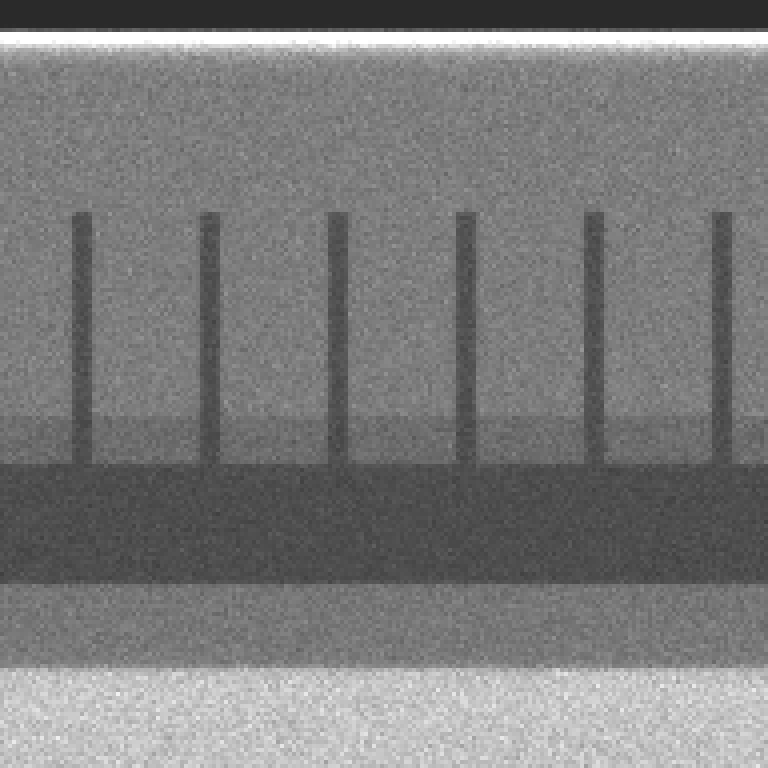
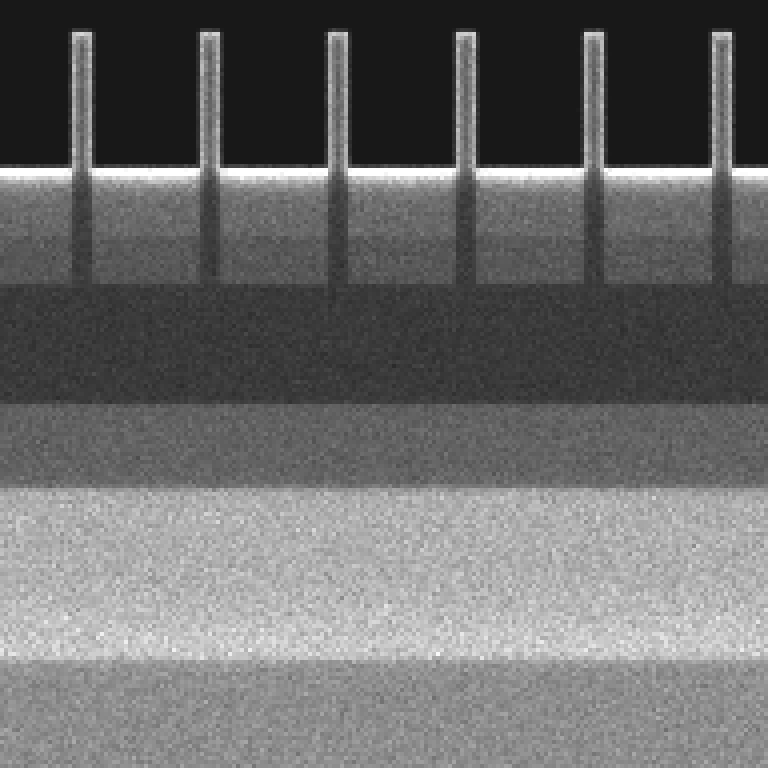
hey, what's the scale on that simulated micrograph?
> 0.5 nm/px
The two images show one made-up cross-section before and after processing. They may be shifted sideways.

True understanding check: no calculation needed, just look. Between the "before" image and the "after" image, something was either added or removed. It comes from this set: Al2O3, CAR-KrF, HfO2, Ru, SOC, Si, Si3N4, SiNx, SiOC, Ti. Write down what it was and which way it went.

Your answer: SOC (removed)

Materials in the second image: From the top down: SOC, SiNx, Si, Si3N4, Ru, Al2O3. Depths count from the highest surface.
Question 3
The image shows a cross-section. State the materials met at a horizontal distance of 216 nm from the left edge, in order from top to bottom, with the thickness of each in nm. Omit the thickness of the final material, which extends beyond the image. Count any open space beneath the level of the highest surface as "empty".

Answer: empty 68, SOC 34, SiNx 24, Si 60, Si3N4 42, Ru 86, Al2O3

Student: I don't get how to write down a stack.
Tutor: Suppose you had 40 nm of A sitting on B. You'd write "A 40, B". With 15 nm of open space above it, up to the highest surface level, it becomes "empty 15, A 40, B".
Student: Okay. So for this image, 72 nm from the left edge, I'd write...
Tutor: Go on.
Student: empty 68, SOC 34, SiNx 24, Si 60, Si3N4 42, Ru 86, Al2O3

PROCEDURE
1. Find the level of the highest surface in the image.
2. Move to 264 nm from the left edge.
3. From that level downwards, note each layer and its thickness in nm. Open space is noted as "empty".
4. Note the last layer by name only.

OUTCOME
empty 68, SOC 34, SiNx 24, Si 60, Si3N4 42, Ru 86, Al2O3